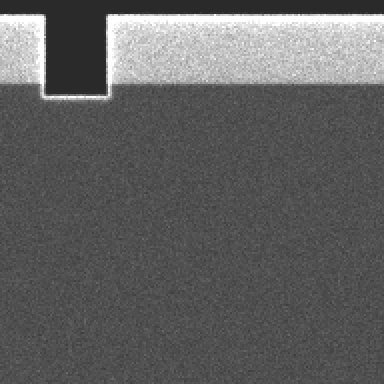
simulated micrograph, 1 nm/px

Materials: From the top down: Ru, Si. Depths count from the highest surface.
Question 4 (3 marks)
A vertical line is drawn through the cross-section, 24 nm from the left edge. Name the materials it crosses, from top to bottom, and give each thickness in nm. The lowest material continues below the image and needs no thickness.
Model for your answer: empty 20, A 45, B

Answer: Ru 68, Si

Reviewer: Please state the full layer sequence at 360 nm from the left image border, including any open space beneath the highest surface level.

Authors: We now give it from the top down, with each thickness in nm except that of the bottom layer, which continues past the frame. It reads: Ru 68, Si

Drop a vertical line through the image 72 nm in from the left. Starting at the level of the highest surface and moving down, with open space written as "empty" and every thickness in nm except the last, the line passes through empty 80, Si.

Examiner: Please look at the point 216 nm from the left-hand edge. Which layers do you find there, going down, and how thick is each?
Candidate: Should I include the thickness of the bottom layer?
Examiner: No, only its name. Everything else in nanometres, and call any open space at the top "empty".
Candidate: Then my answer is Ru 68, Si